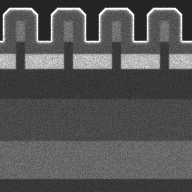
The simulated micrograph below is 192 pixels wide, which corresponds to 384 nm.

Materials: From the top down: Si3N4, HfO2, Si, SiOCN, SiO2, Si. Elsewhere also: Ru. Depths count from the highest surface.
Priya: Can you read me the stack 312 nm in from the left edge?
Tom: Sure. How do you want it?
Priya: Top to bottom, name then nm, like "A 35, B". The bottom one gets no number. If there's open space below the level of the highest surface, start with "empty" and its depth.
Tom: Si3N4 92, HfO2 30, Si 60, SiOCN 84, SiO2 76, Si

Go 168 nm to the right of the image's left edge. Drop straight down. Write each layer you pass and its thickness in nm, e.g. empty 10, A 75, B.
empty 10, Si3N4 82, HfO2 30, Si 60, SiOCN 84, SiO2 76, Si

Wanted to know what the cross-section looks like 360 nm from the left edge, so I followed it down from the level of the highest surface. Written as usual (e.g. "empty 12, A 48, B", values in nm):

empty 10, Si3N4 82, HfO2 30, Si 60, SiOCN 84, SiO2 76, Si